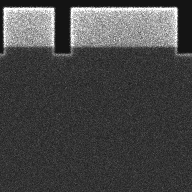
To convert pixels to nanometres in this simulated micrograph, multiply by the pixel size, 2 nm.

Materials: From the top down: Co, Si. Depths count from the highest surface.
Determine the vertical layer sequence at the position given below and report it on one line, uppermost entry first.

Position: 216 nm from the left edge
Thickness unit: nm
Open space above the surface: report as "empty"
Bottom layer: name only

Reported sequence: Co 78, Si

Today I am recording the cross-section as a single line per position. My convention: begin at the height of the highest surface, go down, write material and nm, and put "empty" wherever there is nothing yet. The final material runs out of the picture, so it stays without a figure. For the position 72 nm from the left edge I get Co 78, Si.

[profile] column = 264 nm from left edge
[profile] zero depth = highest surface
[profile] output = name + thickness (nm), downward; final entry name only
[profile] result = Co 78, Si